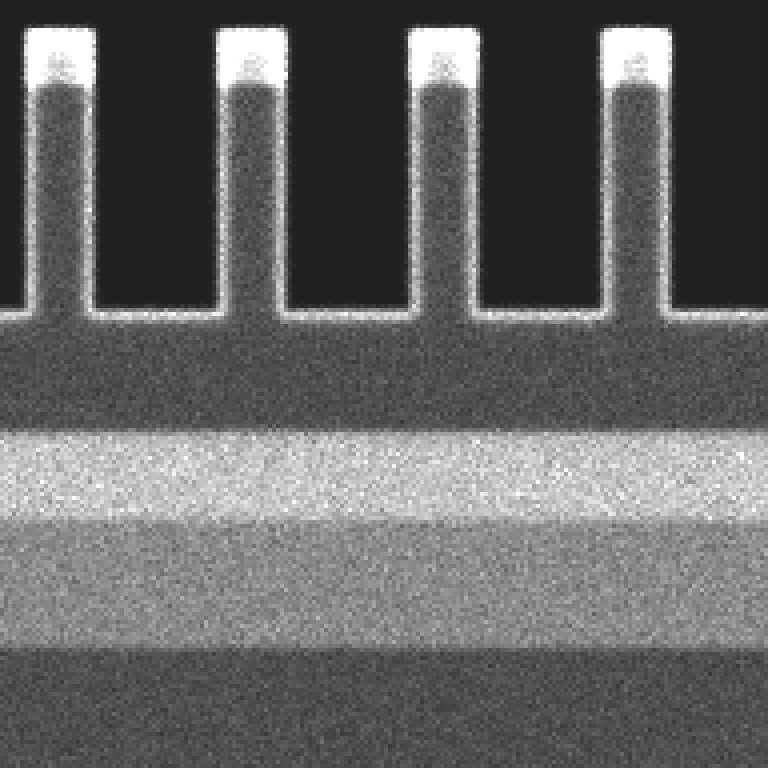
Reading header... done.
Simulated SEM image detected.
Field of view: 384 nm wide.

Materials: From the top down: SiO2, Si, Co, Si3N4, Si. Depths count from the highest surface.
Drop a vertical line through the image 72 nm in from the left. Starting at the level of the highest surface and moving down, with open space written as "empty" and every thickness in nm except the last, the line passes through empty 140, Si 60, Co 44, Si3N4 64, Si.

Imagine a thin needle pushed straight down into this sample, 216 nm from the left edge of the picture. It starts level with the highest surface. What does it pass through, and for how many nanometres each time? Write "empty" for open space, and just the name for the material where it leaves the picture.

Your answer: SiO2 26, Si 174, Co 44, Si3N4 64, Si